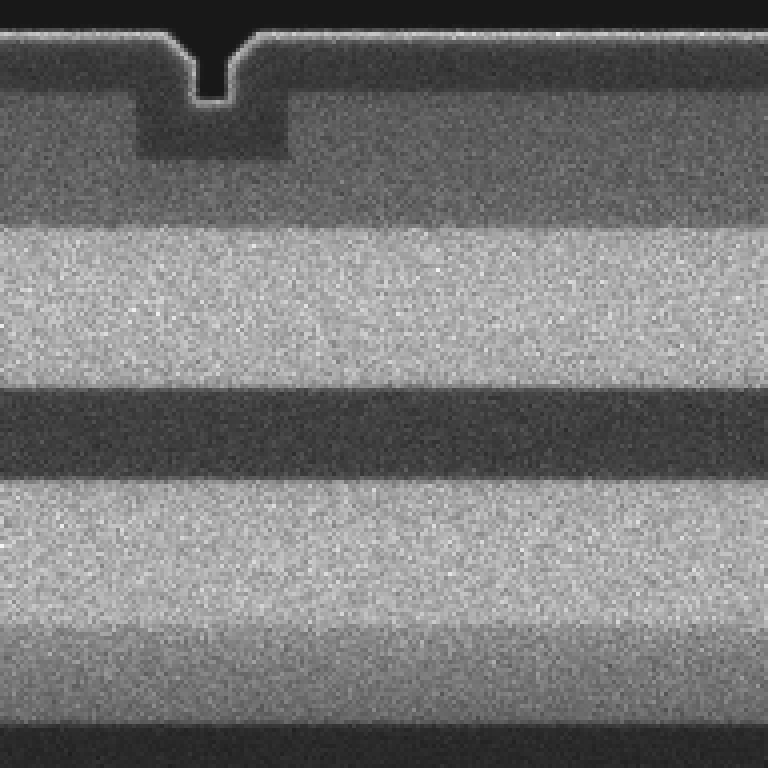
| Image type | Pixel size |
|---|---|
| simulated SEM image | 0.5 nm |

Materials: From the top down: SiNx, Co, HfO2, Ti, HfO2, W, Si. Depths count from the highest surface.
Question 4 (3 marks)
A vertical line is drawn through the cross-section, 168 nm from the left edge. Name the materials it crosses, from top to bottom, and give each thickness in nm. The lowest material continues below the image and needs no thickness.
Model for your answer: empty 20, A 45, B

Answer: SiNx 30, Co 68, HfO2 80, Ti 46, HfO2 72, W 50, Si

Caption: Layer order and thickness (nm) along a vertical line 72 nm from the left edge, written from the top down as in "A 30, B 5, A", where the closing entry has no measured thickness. SiNx 64, Co 34, HfO2 80, Ti 46, HfO2 72, W 50, Si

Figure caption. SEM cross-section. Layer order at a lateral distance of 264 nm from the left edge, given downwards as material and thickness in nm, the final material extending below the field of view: SiNx 30, Co 68, HfO2 80, Ti 46, HfO2 72, W 50, Si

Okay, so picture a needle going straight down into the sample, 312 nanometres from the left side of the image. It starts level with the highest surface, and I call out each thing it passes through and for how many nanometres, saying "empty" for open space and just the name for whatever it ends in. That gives SiNx 30, Co 68, HfO2 80, Ti 46, HfO2 72, W 50, Si